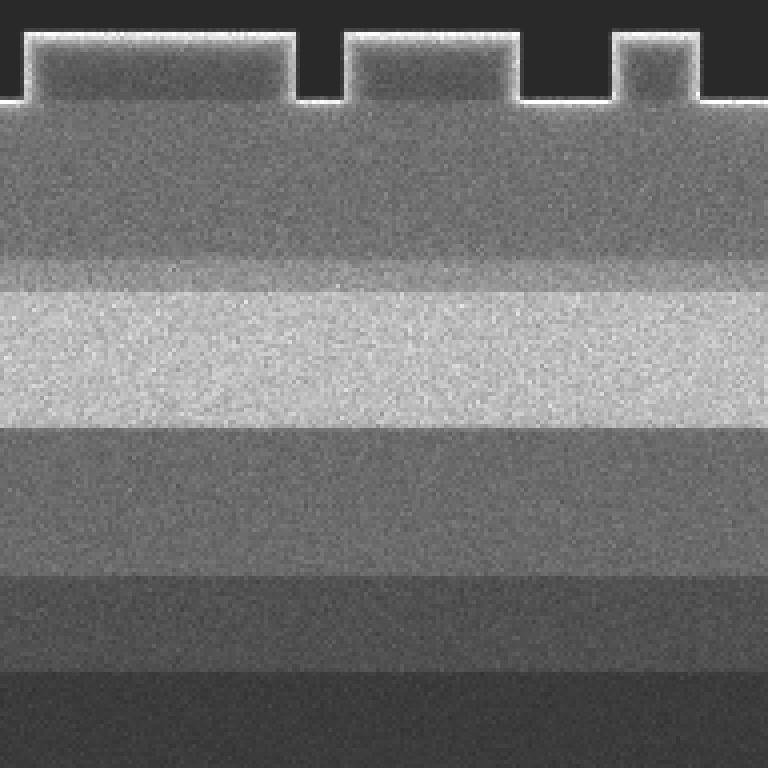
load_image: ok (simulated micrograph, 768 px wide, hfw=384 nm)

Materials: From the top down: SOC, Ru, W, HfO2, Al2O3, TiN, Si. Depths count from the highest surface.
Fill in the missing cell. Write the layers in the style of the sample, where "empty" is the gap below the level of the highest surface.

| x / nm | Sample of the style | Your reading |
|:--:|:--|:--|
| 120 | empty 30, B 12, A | SOC 34, Ru 80, W 16, HfO2 68, Al2O3 74, TiN 48, Si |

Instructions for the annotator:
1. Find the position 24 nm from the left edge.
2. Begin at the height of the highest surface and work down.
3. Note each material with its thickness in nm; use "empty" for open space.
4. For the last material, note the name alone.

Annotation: SOC 34, Ru 80, W 16, HfO2 68, Al2O3 74, TiN 48, Si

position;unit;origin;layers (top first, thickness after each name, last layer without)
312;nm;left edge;SOC 34, Ru 80, W 16, HfO2 68, Al2O3 74, TiN 48, Si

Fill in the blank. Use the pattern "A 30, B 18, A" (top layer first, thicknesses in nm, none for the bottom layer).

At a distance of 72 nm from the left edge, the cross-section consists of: SOC 34, Ru 80, W 16, HfO2 68, Al2O3 74, TiN 48, Si